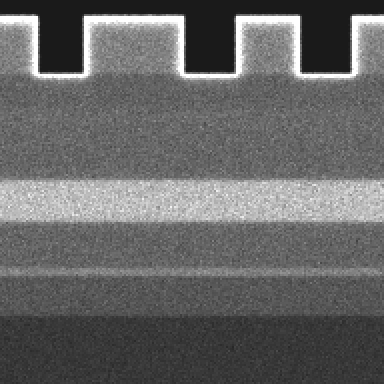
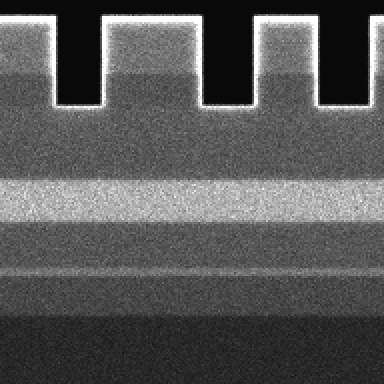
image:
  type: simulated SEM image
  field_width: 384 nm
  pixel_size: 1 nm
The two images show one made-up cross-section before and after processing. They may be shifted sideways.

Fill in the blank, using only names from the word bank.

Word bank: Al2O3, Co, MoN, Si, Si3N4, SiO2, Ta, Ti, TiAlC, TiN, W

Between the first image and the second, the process removed Si3N4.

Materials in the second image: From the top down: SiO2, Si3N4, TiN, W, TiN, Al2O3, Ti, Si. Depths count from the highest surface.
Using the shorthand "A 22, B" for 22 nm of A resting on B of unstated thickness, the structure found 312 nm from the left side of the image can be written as SiO2 58, Si3N4 32, TiN 74, W 42, TiN 46, Al2O3 8, Ti 40, Si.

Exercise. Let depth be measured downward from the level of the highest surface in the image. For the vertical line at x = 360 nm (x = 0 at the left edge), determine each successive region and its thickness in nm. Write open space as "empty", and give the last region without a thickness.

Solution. empty 90, TiN 74, W 42, TiN 46, Al2O3 8, Ti 40, Si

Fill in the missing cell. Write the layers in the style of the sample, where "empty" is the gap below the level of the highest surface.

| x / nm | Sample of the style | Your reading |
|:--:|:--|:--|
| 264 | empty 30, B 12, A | SiO2 58, Si3N4 32, TiN 74, W 42, TiN 46, Al2O3 8, Ti 40, Si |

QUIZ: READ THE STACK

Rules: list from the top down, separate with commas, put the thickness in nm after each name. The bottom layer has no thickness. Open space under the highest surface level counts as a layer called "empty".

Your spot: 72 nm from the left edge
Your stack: empty 90, TiN 74, W 42, TiN 46, Al2O3 8, Ti 40, Si